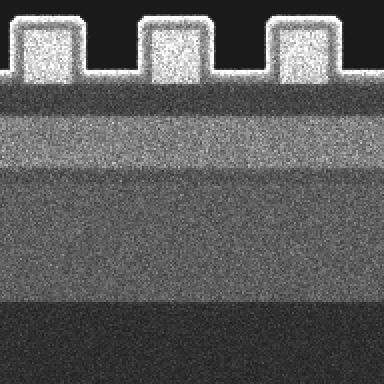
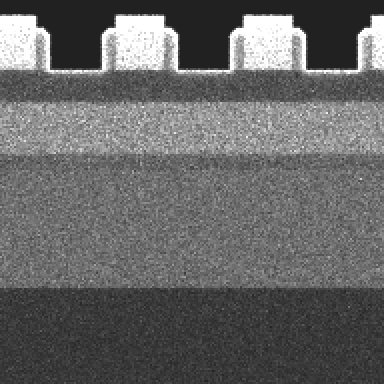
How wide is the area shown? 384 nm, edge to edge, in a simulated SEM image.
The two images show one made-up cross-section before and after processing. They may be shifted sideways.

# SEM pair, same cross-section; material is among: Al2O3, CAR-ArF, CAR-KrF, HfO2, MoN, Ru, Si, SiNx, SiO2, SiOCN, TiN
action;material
removed;Al2O3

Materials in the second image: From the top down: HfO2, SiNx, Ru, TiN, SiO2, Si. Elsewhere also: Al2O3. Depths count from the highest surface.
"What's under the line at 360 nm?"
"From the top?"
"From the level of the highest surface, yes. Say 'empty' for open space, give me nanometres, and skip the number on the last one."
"empty 16, Al2O3 38, SiNx 32, Ru 52, TiN 16, SiO2 118, Si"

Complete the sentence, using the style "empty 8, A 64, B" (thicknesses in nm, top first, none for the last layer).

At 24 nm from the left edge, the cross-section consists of HfO2 54, SiNx 32, Ru 52, TiN 16, SiO2 118, Si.